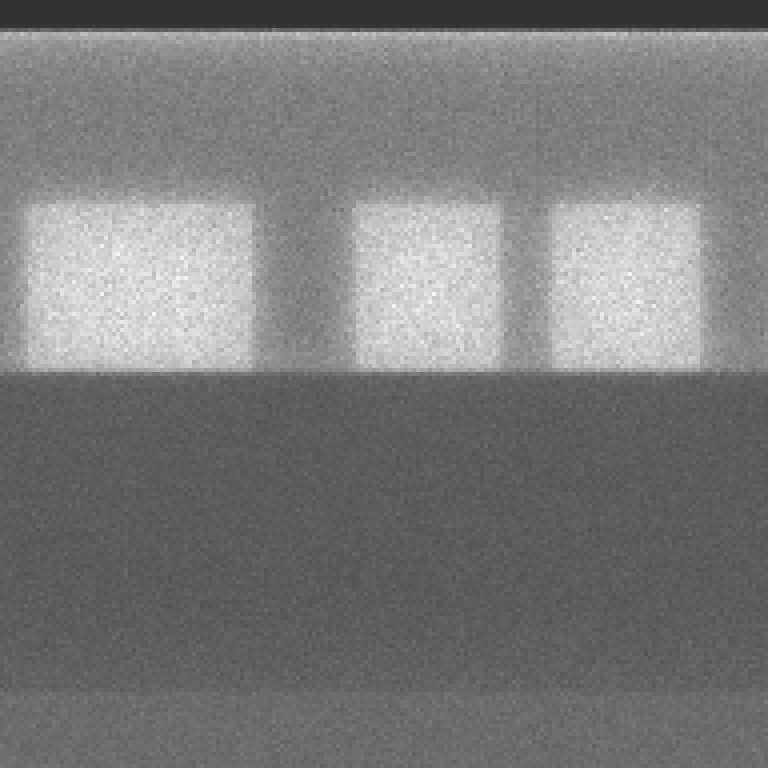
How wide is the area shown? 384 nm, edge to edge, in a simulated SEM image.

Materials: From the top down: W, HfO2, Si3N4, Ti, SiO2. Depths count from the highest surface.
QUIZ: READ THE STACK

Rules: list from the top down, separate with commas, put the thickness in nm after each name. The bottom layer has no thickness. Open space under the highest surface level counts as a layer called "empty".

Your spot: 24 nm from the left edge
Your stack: W 86, HfO2 84, Si3N4 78, Ti 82, SiO2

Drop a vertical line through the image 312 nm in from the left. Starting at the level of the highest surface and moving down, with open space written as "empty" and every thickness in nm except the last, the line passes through W 86, HfO2 84, Si3N4 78, Ti 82, SiO2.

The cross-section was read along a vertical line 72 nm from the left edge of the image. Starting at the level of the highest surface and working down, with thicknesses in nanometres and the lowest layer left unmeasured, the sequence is W 86, HfO2 84, Si3N4 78, Ti 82, SiO2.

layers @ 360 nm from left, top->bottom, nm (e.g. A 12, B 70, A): W 170, Si3N4 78, Ti 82, SiO2